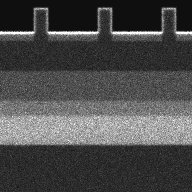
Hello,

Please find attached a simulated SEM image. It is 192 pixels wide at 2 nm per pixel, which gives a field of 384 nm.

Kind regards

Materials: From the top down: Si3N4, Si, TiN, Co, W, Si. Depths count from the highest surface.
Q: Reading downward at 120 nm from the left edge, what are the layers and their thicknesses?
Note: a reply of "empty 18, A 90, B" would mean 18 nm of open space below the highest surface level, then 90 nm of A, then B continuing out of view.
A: empty 48, Si3N4 18, Si 60, TiN 60, Co 30, W 58, Si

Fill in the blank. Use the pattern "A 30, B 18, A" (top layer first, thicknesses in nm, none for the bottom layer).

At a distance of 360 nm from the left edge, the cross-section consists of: empty 48, Si3N4 18, Si 60, TiN 60, Co 30, W 58, Si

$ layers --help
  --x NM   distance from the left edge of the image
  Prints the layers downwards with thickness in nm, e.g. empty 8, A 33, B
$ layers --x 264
empty 48, Si3N4 18, Si 60, TiN 60, Co 30, W 58, Si